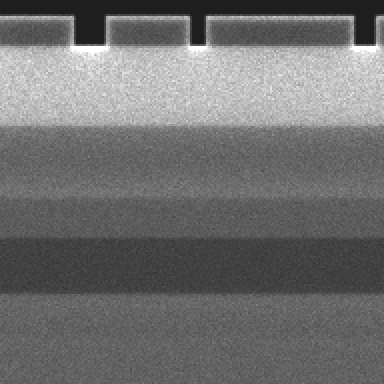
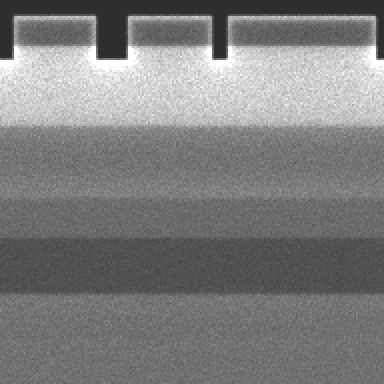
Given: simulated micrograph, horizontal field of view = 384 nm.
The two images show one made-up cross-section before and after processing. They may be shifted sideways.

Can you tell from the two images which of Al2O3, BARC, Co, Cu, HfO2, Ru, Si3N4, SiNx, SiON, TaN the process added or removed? Yes, it removed HfO2.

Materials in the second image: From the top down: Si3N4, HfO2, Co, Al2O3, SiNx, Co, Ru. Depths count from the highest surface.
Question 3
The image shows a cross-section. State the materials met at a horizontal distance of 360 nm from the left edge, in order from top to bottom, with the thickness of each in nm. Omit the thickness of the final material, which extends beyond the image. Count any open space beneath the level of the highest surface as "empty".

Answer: Si3N4 30, HfO2 80, Co 72, Al2O3 40, SiNx 56, Co 44, Ru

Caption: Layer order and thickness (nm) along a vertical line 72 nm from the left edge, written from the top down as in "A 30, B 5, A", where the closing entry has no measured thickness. Si3N4 30, HfO2 80, Co 72, Al2O3 40, SiNx 56, Co 44, Ru